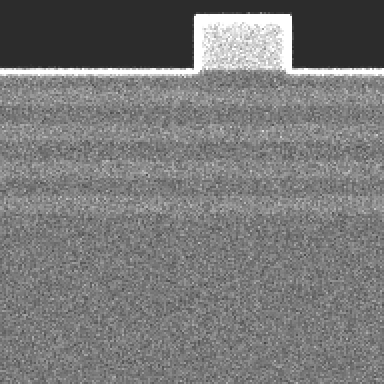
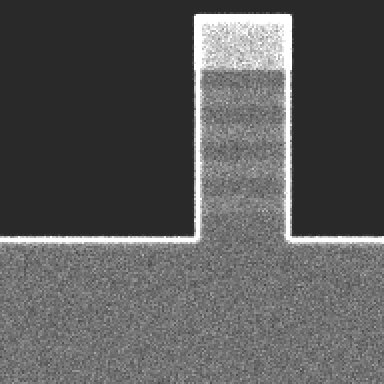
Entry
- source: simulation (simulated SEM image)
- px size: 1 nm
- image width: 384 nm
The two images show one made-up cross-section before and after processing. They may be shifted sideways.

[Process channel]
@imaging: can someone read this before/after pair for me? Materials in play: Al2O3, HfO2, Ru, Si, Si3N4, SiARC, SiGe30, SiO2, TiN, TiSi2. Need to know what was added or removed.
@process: Si and SiGe30 removed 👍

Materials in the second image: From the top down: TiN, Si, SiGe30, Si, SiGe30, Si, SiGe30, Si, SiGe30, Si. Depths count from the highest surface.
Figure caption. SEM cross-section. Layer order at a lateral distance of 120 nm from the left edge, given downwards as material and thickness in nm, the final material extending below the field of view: empty 222, Si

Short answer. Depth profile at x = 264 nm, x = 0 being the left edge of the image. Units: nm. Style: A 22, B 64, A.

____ TiN 54, Si 18, SiGe30 18, Si 18, SiGe30 18, Si 18, SiGe30 18, Si 18, SiGe30 18, Si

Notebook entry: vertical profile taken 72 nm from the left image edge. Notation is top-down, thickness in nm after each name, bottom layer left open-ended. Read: empty 222, Si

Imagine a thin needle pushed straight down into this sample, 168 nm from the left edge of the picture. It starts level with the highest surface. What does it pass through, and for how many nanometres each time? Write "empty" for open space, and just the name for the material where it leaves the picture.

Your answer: empty 222, Si